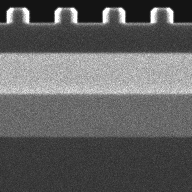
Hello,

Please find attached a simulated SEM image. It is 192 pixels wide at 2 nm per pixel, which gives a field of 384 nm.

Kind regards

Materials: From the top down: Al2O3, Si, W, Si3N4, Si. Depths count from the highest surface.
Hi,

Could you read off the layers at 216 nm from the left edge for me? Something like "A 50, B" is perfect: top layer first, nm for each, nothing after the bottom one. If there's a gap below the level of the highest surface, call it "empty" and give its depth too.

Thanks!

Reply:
Al2O3 30, Si 60, W 82, Si3N4 86, Si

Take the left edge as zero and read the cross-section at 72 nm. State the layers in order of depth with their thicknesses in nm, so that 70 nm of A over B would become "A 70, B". empty 30, Si 60, W 82, Si3N4 86, Si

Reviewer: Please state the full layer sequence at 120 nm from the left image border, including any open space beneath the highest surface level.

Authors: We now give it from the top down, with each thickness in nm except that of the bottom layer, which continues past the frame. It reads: Al2O3 30, Si 60, W 82, Si3N4 86, Si